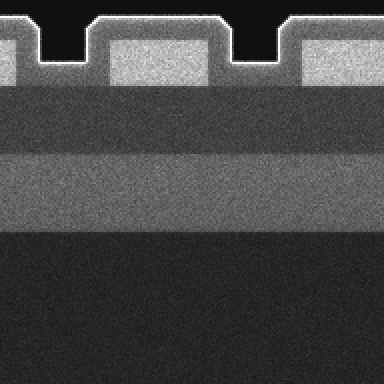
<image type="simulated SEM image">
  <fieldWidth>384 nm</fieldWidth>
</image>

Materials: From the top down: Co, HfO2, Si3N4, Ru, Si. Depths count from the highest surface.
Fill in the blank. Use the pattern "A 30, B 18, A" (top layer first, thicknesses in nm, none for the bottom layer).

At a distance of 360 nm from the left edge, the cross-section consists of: Co 24, HfO2 46, Si3N4 68, Ru 78, Si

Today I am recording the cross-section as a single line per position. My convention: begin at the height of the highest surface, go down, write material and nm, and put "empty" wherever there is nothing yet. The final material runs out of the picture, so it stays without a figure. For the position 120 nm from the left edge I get Co 24, HfO2 46, Si3N4 68, Ru 78, Si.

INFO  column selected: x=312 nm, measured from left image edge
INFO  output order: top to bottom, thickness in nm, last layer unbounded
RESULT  Co 24, HfO2 46, Si3N4 68, Ru 78, Si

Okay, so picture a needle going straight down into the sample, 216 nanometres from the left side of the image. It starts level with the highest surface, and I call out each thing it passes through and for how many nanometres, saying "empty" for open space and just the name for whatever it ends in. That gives Co 70, Si3N4 68, Ru 78, Si